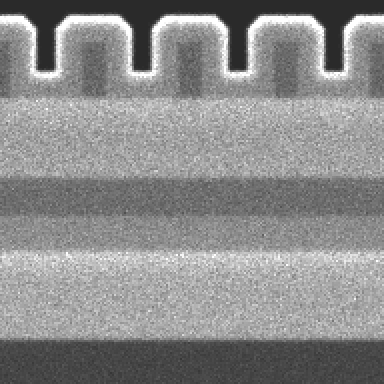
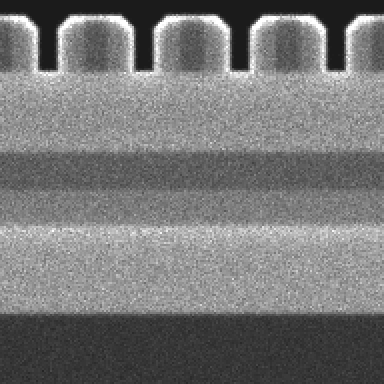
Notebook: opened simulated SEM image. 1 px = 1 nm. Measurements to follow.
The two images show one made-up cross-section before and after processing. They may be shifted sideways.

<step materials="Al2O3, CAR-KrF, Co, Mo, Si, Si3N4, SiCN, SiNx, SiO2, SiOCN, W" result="removed SiO2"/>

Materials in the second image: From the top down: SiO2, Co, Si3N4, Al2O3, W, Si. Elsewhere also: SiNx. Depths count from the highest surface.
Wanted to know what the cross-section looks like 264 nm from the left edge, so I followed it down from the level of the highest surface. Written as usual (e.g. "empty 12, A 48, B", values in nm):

SiO2 56, Co 80, Si3N4 38, Al2O3 36, W 88, Si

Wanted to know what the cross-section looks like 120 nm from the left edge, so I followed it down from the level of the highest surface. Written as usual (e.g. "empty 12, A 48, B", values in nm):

SiO2 56, Co 80, Si3N4 38, Al2O3 36, W 88, Si